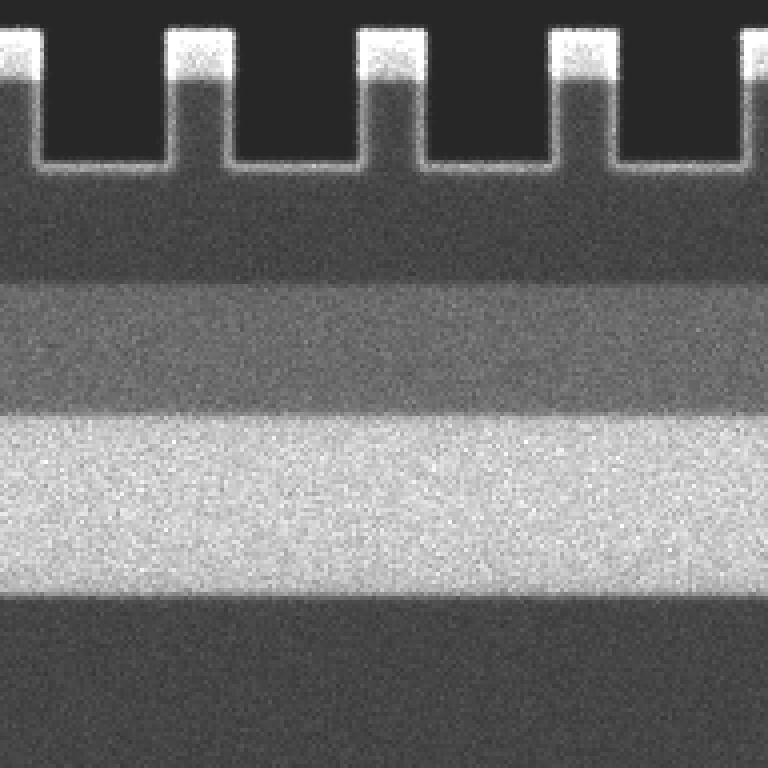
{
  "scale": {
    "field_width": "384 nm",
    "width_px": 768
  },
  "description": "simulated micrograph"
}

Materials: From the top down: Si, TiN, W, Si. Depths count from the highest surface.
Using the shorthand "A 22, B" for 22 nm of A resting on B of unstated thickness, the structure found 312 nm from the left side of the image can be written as empty 66, Si 60, TiN 66, W 90, Si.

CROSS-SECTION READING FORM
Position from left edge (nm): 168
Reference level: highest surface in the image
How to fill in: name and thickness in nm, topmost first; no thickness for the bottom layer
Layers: empty 66, Si 60, TiN 66, W 90, Si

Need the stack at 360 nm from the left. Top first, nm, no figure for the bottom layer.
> empty 66, Si 60, TiN 66, W 90, Si